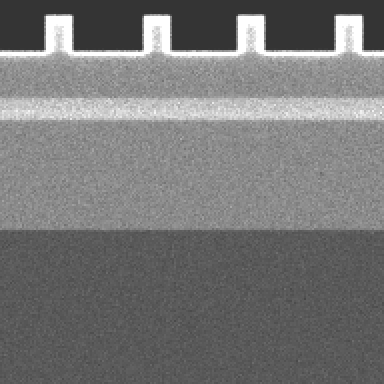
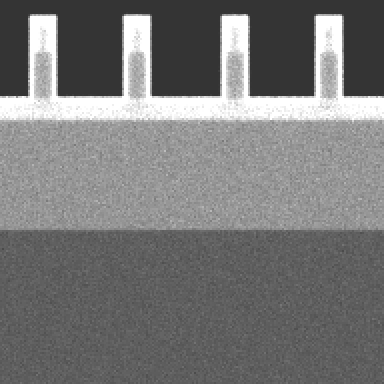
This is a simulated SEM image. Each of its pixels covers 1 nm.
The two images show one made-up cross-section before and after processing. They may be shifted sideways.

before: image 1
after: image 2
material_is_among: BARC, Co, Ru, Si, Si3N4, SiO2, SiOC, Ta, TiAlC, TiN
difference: TiN, removed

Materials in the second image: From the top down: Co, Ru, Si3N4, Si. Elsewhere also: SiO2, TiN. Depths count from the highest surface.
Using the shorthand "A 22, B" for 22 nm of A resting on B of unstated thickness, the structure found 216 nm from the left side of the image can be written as empty 82, Co 12, Ru 10, Si3N4 110, Si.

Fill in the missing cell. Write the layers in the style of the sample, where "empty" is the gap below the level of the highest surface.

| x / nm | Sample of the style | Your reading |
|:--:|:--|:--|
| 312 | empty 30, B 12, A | empty 82, Co 12, Ru 10, Si3N4 110, Si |